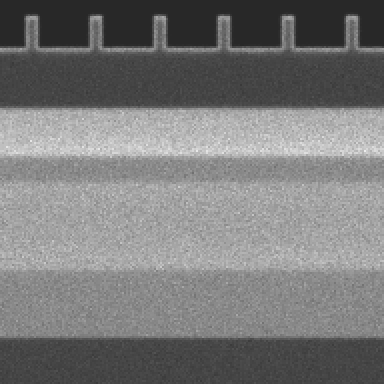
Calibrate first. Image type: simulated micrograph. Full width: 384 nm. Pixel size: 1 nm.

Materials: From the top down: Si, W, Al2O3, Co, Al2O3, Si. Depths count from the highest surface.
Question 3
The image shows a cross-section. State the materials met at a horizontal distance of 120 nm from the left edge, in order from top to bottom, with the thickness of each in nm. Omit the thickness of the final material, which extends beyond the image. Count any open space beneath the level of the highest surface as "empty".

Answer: empty 32, Si 60, W 48, Al2O3 26, Co 88, Al2O3 68, Si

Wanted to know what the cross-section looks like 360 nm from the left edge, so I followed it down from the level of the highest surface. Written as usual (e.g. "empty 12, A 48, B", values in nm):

empty 32, Si 60, W 48, Al2O3 26, Co 88, Al2O3 68, Si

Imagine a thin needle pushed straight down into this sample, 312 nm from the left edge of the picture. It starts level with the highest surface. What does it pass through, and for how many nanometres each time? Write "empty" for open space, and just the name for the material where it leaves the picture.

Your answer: empty 32, Si 60, W 48, Al2O3 26, Co 88, Al2O3 68, Si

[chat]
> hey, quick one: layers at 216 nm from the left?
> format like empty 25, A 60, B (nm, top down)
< empty 32, Si 60, W 48, Al2O3 26, Co 88, Al2O3 68, Si